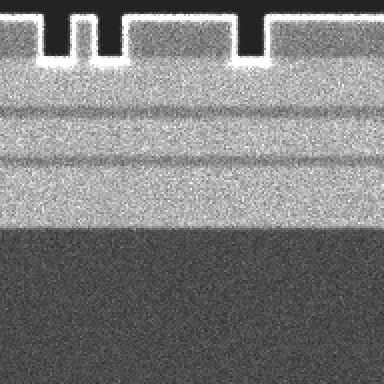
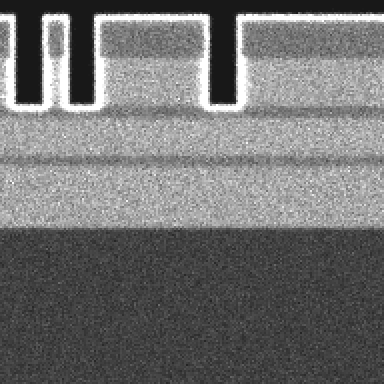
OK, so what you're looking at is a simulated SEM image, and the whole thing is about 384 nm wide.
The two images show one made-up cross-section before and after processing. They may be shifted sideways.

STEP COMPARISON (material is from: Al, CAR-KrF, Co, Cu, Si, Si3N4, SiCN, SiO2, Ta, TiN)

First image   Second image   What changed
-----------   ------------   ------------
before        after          SiO2, removed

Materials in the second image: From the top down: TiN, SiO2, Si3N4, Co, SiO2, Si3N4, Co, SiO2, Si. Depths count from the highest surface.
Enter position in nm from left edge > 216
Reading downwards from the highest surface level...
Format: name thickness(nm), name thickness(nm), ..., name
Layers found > empty 90, Si3N4 12, SiO2 38, Si3N4 10, Co 38, SiO2 24, Si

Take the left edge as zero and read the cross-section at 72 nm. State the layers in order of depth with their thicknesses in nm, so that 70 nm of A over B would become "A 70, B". empty 90, Si3N4 12, SiO2 38, Si3N4 10, Co 38, SiO2 24, Si